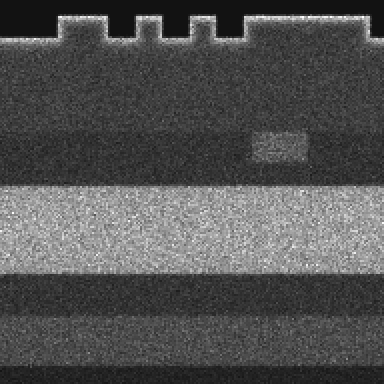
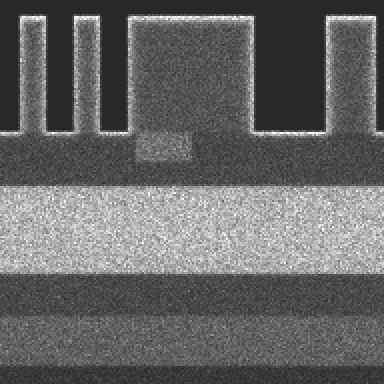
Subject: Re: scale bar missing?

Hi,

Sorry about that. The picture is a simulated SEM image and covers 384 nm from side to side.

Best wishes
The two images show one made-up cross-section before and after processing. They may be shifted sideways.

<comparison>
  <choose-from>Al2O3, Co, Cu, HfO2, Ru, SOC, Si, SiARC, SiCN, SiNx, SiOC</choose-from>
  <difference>SOC removed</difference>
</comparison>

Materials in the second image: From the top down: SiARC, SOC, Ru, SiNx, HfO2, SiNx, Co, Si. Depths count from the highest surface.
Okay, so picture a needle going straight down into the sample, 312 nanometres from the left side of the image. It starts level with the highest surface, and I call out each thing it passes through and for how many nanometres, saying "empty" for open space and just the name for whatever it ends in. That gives empty 116, SiNx 54, HfO2 88, SiNx 42, Co 50, Si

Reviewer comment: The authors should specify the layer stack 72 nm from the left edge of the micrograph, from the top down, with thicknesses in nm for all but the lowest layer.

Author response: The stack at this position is empty 116, SiNx 54, HfO2 88, SiNx 42, Co 50, Si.